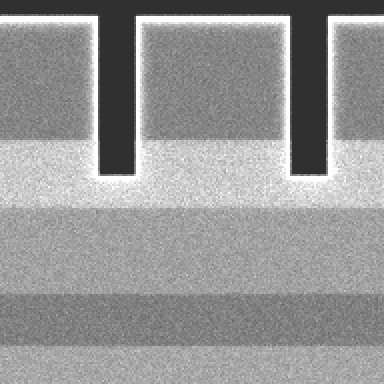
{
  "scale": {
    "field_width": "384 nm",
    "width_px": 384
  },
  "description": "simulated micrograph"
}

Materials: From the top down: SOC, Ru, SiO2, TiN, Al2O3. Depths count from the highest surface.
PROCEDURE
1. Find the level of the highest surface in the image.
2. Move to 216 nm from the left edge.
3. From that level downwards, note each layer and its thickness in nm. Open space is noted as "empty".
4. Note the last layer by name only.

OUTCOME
SOC 124, Ru 68, SiO2 86, TiN 52, Al2O3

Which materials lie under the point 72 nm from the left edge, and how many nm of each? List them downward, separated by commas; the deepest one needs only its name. SOC 124, Ru 68, SiO2 86, TiN 52, Al2O3